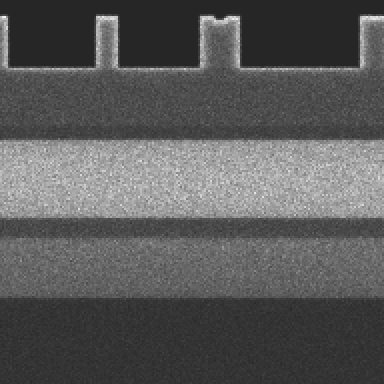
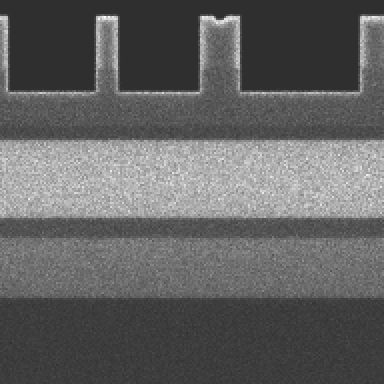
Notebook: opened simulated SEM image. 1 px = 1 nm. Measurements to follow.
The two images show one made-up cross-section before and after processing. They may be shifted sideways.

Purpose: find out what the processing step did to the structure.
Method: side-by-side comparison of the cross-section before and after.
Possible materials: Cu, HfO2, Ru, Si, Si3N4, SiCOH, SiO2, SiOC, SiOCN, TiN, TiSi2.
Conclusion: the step removed TiN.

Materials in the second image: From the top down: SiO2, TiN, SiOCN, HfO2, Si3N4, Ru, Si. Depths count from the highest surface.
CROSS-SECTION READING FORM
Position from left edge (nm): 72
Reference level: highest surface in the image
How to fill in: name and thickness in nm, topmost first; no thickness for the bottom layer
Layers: empty 76, TiN 34, SiOCN 14, HfO2 78, Si3N4 20, Ru 60, Si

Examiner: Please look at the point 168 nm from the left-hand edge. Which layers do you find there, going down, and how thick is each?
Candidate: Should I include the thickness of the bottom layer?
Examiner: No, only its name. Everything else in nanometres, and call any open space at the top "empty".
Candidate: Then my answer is empty 76, TiN 34, SiOCN 14, HfO2 78, Si3N4 20, Ru 60, Si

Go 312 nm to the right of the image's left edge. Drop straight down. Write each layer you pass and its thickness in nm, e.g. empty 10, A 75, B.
empty 76, TiN 34, SiOCN 14, HfO2 78, Si3N4 20, Ru 60, Si